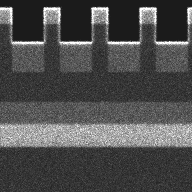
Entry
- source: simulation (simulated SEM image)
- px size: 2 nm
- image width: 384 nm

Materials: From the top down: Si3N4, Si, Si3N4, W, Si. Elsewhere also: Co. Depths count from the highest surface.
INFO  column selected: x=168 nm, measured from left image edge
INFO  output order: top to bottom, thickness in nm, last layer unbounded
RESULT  empty 68, Si3N4 60, Si 60, Si3N4 44, W 46, Si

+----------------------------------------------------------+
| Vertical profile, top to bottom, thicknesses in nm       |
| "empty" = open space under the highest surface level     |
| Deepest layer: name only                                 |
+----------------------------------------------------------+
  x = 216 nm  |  empty 68, Si3N4 60, Si 60, Si3N4 44, W 46, Si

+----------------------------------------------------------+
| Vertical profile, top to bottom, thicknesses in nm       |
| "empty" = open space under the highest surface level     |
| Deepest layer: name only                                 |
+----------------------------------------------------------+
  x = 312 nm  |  empty 68, Si3N4 60, Si 60, Si3N4 44, W 46, Si